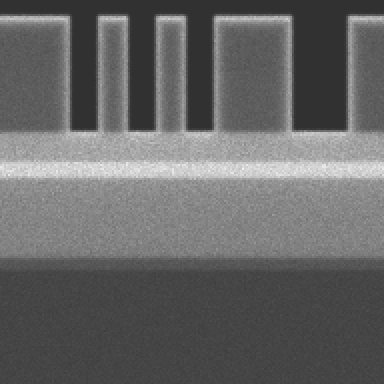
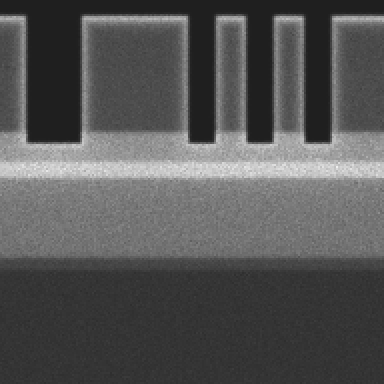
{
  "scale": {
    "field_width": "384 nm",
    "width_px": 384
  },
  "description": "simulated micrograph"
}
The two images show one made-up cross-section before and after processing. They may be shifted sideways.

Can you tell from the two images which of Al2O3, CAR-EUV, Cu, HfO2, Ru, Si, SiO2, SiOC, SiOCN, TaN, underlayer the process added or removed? Yes, it removed Ru.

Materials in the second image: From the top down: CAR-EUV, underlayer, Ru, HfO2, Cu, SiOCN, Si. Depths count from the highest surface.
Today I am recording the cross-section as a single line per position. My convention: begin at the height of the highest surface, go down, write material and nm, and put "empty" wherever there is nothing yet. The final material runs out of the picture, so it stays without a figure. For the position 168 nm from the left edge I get CAR-EUV 56, underlayer 60, Ru 30, HfO2 16, Cu 80, SiOCN 12, Si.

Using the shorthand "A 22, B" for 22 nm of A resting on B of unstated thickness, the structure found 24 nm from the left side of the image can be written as CAR-EUV 56, underlayer 60, Ru 30, HfO2 16, Cu 80, SiOCN 12, Si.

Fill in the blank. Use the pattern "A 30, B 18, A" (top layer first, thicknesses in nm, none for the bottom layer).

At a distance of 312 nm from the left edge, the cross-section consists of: empty 128, Ru 18, HfO2 16, Cu 80, SiOCN 12, Si